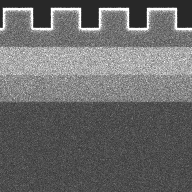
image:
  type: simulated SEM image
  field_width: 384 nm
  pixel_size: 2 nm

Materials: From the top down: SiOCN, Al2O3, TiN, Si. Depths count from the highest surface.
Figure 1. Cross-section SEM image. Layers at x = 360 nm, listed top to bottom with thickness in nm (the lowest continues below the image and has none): empty 40, SiOCN 38, Al2O3 56, TiN 54, Si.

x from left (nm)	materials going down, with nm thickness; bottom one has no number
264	empty 40, SiOCN 38, Al2O3 56, TiN 54, Si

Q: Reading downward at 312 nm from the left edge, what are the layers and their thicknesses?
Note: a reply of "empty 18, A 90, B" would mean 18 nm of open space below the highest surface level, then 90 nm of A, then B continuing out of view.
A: SiOCN 78, Al2O3 56, TiN 54, Si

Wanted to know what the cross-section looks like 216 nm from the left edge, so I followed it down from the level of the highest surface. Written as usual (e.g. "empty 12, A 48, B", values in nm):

SiOCN 78, Al2O3 56, TiN 54, Si